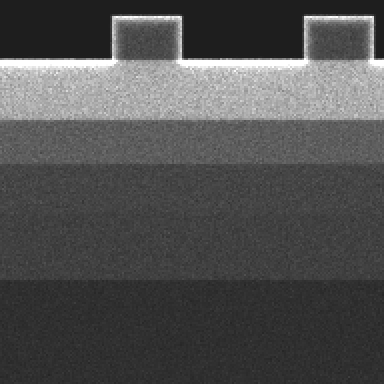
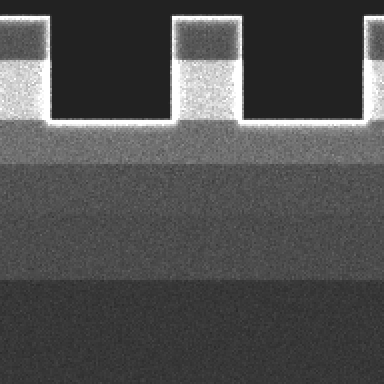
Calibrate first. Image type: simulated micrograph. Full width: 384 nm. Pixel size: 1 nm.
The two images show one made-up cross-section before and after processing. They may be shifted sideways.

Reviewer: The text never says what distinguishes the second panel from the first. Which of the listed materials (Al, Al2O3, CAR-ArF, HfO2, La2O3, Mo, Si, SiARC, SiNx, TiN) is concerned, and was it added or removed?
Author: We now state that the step removed HfO2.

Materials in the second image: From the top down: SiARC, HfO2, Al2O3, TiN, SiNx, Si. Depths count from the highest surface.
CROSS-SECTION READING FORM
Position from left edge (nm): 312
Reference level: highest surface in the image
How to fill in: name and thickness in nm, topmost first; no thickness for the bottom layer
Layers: empty 104, Al2O3 44, TiN 50, SiNx 66, Si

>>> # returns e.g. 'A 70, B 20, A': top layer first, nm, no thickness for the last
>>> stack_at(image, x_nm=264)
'empty 104, Al2O3 44, TiN 50, SiNx 66, Si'